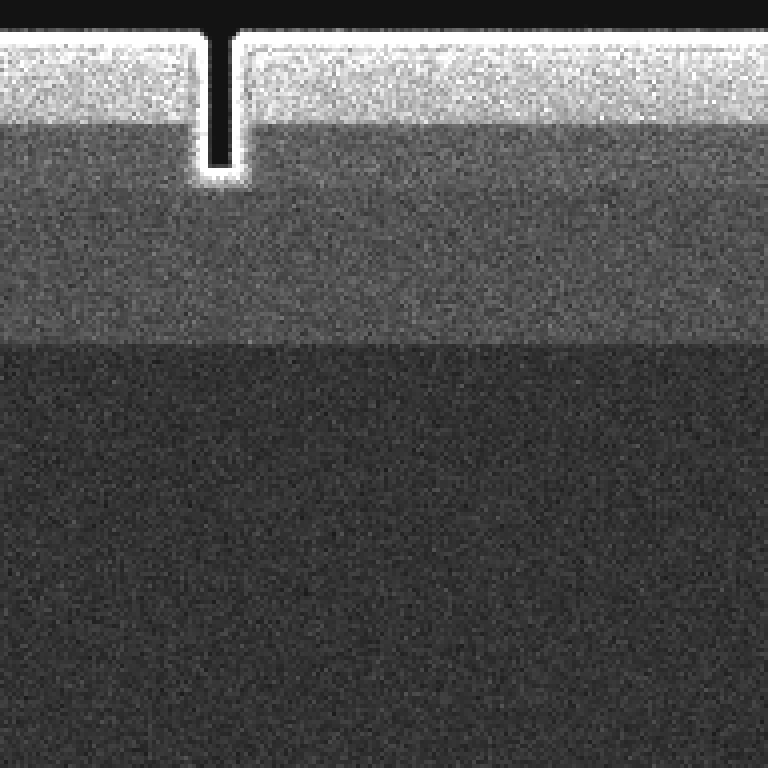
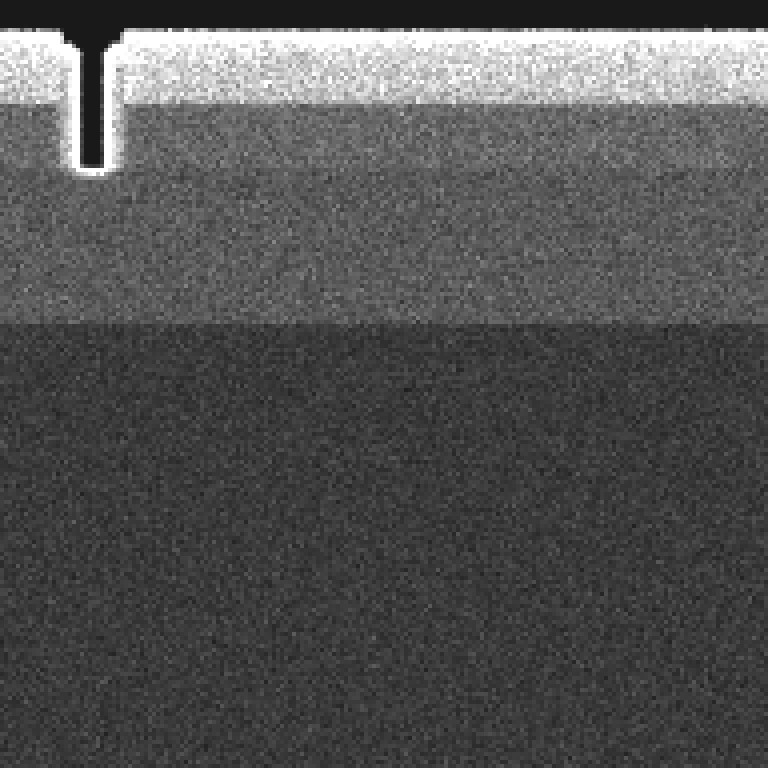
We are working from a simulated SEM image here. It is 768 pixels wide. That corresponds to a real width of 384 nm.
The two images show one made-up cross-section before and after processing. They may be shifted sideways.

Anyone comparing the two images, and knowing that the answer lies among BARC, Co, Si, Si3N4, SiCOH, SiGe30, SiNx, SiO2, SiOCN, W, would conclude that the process removed SiO2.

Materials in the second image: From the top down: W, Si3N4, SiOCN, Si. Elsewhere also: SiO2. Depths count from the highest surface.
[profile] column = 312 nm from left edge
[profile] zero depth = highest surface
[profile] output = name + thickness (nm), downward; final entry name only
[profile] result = W 36, Si3N4 32, SiOCN 78, Si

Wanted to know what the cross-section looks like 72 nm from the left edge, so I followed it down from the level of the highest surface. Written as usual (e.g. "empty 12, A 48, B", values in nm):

W 36, Si3N4 32, SiOCN 78, Si